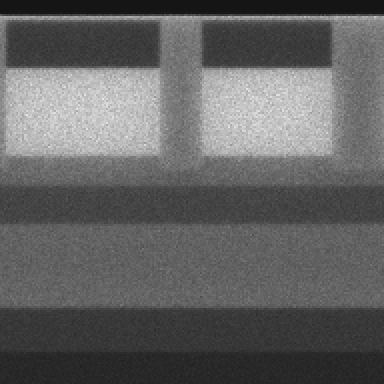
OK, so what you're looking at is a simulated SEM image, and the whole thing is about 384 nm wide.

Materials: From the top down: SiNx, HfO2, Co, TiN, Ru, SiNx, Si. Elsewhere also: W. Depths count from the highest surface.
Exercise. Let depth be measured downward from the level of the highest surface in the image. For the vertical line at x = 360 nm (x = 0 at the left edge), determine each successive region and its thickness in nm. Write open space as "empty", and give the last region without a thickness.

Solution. W 154, Co 16, TiN 38, Ru 84, SiNx 44, Si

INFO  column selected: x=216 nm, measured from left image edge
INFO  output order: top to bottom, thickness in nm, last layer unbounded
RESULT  SiNx 52, HfO2 88, Co 30, TiN 38, Ru 84, SiNx 44, Si